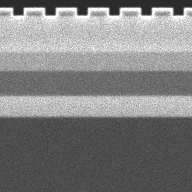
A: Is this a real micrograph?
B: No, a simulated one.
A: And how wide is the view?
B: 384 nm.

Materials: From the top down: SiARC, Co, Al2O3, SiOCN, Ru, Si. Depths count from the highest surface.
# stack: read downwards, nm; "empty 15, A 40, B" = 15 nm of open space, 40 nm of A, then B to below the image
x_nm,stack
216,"SiARC 16, Co 72, Al2O3 38, SiOCN 50, Ru 42, Si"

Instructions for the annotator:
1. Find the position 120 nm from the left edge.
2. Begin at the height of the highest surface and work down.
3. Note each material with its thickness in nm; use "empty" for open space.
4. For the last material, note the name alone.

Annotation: SiARC 16, Co 72, Al2O3 38, SiOCN 50, Ru 42, Si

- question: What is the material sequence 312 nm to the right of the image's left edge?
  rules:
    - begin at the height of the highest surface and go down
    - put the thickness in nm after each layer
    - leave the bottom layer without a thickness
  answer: SiARC 16, Co 72, Al2O3 38, SiOCN 50, Ru 42, Si